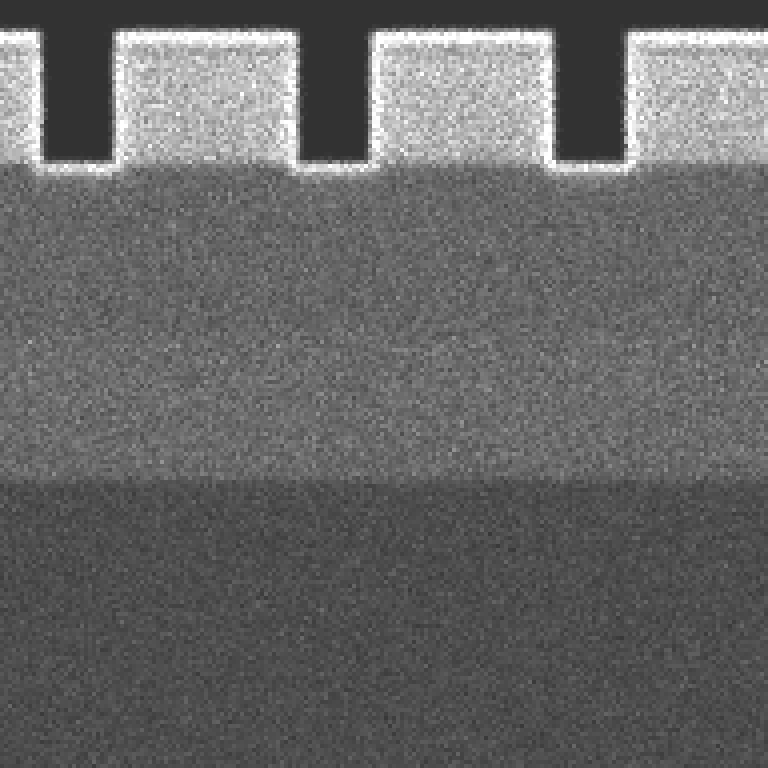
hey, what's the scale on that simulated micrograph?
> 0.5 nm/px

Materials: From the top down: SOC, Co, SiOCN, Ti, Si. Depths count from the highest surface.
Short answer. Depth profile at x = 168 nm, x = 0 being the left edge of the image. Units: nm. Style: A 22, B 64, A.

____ empty 66, SiOCN 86, Ti 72, Si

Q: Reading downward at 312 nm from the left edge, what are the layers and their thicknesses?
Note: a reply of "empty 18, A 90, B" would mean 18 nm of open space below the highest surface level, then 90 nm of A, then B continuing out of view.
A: empty 66, SiOCN 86, Ti 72, Si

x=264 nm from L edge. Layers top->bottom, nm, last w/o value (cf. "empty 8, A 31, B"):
SOC 12, Co 54, SiOCN 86, Ti 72, Si